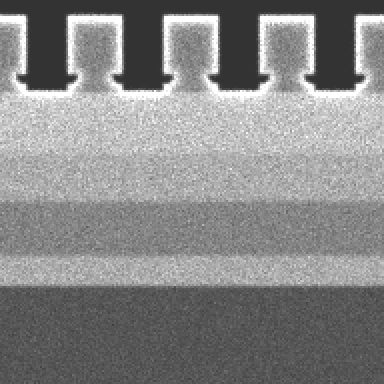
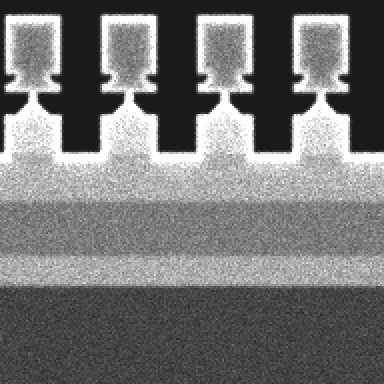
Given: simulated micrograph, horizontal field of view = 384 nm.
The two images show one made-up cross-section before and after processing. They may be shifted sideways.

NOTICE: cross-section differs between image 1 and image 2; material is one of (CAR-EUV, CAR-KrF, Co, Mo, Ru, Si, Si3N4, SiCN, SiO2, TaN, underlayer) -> removed: Ru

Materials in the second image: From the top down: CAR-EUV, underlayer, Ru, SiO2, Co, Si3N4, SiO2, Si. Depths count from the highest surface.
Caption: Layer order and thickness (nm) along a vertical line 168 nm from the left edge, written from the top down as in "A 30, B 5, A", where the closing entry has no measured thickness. empty 138, SiO2 12, Co 36, Si3N4 54, SiO2 30, Si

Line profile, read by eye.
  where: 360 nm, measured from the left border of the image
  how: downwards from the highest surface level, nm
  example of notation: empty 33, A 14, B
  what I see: empty 138, SiO2 12, Co 36, Si3N4 54, SiO2 30, Si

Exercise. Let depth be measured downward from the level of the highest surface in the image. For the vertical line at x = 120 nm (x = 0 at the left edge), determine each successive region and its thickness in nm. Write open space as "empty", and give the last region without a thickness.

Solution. CAR-EUV 58, underlayer 18, empty 16, Ru 46, SiO2 12, Co 36, Si3N4 54, SiO2 30, Si